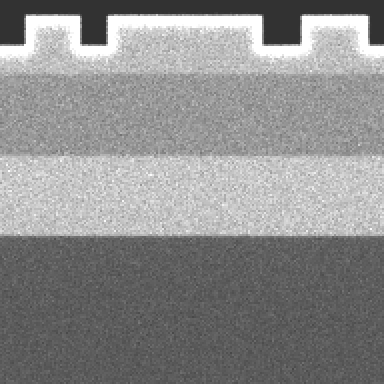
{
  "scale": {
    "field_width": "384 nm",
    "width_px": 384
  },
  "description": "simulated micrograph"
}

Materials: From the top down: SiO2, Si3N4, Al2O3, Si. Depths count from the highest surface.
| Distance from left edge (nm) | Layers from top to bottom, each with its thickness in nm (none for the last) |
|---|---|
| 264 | empty 30, SiO2 28, Si3N4 82, Al2O3 80, Si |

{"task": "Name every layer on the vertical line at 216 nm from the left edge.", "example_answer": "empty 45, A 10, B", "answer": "SiO2 58, Si3N4 82, Al2O3 80, Si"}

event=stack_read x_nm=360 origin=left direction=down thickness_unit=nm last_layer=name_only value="SiO2 58, Si3N4 82, Al2O3 80, Si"